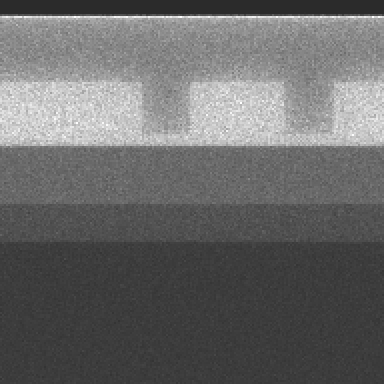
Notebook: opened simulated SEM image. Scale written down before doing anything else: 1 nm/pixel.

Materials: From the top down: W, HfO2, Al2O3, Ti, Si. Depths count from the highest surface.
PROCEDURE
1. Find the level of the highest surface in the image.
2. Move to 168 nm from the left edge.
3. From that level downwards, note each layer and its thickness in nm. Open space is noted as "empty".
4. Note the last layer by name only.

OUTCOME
W 118, HfO2 12, Al2O3 58, Ti 38, Si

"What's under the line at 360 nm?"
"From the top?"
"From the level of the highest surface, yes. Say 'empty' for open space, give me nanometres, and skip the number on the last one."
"W 66, HfO2 64, Al2O3 58, Ti 38, Si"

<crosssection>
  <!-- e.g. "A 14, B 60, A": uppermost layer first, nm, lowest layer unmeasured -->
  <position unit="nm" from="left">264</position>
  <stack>W 66, HfO2 64, Al2O3 58, Ti 38, Si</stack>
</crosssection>